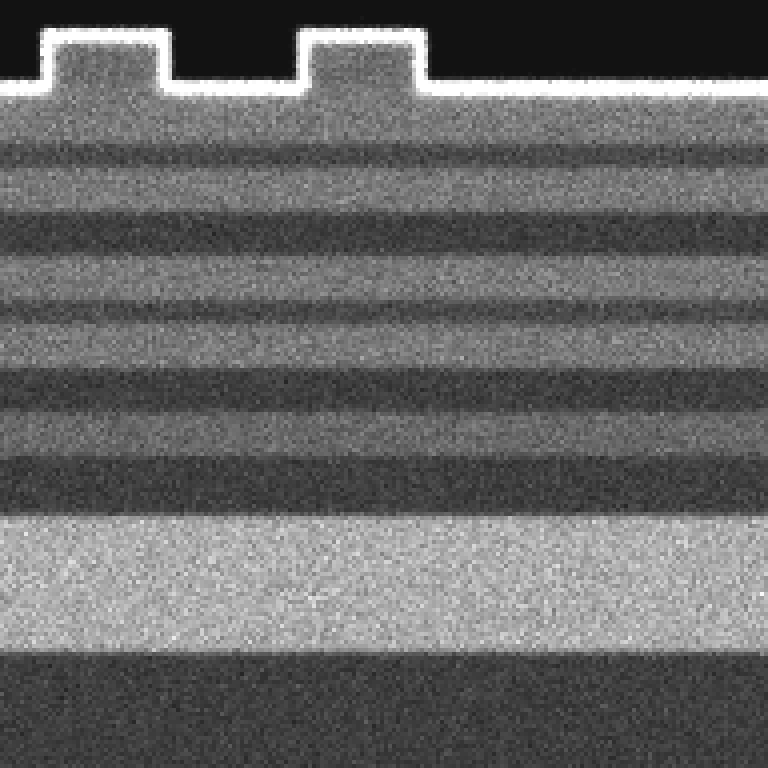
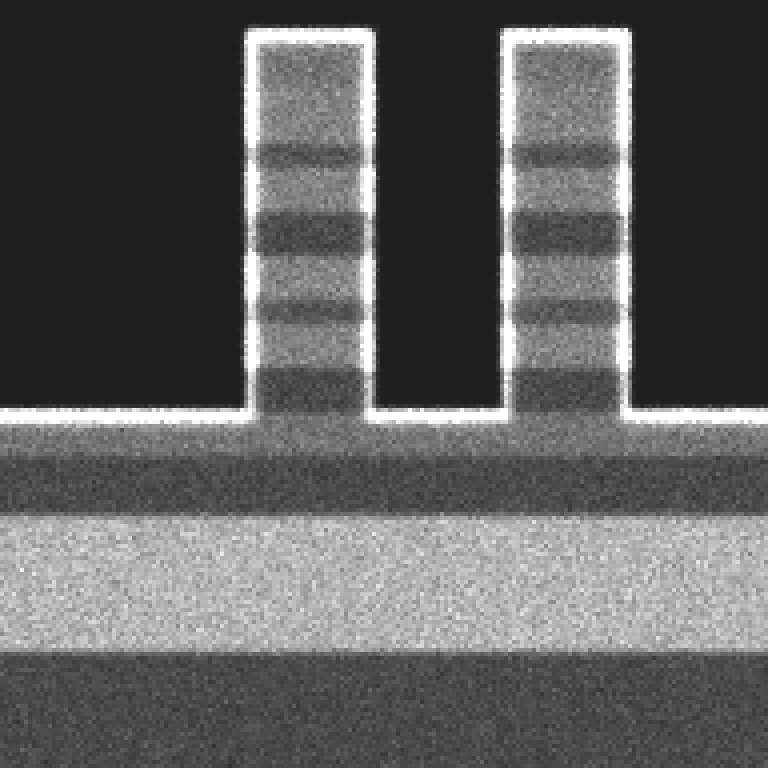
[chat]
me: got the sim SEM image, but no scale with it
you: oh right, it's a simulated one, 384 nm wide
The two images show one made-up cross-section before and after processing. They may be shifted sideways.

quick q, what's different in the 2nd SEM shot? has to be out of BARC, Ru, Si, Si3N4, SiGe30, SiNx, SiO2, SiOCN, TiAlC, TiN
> Si and Si3N4 and SiGe30 removed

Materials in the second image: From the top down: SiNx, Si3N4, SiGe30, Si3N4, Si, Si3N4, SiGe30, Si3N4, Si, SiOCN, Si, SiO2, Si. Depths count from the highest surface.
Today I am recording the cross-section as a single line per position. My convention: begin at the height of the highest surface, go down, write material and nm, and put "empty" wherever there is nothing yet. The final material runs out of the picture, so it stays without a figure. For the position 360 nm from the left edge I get empty 190, SiOCN 22, Si 30, SiO2 68, Si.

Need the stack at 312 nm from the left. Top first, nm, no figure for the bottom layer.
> SiNx 26, Si3N4 30, SiGe30 12, Si3N4 22, Si 22, Si3N4 22, SiGe30 12, Si3N4 22, Si 22, SiOCN 22, Si 30, SiO2 68, Si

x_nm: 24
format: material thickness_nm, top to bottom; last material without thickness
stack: empty 190, SiOCN 22, Si 30, SiO2 68, Si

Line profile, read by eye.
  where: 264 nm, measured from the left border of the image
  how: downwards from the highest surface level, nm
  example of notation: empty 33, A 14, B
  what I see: SiNx 26, Si3N4 30, SiGe30 12, Si3N4 22, Si 22, Si3N4 22, SiGe30 12, Si3N4 22, Si 22, SiOCN 22, Si 30, SiO2 68, Si